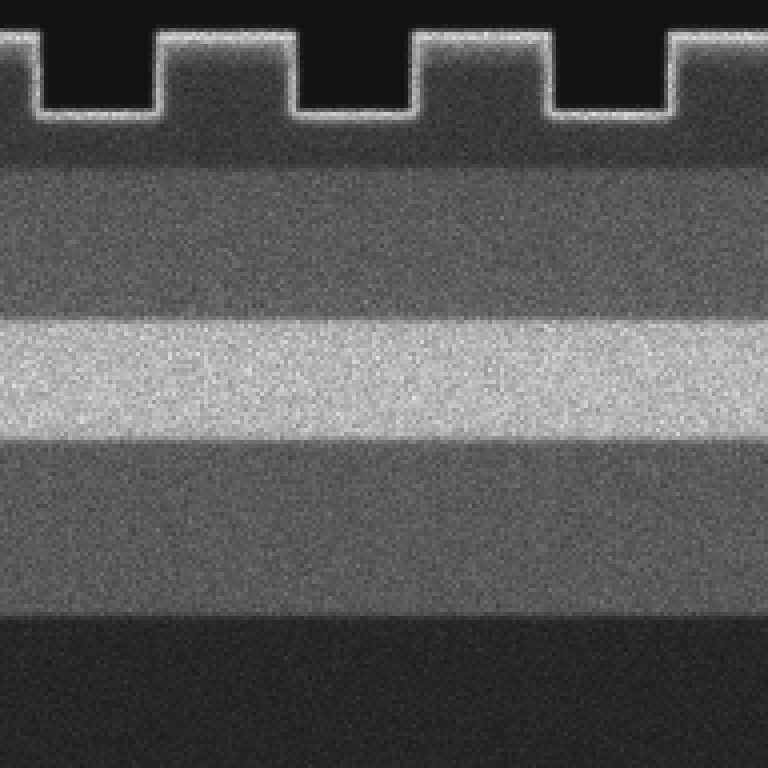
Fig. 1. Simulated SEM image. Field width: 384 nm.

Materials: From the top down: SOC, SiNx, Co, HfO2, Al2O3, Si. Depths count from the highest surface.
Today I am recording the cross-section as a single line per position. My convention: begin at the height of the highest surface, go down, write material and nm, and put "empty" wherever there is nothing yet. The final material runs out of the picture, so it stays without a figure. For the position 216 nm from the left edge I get SOC 16, SiNx 52, Co 76, HfO2 60, Al2O3 88, Si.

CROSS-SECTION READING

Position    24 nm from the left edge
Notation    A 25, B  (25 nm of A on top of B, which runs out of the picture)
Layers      empty 40, SiNx 28, Co 76, HfO2 60, Al2O3 88, Si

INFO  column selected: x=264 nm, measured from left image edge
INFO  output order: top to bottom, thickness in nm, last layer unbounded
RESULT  SOC 16, SiNx 52, Co 76, HfO2 60, Al2O3 88, Si